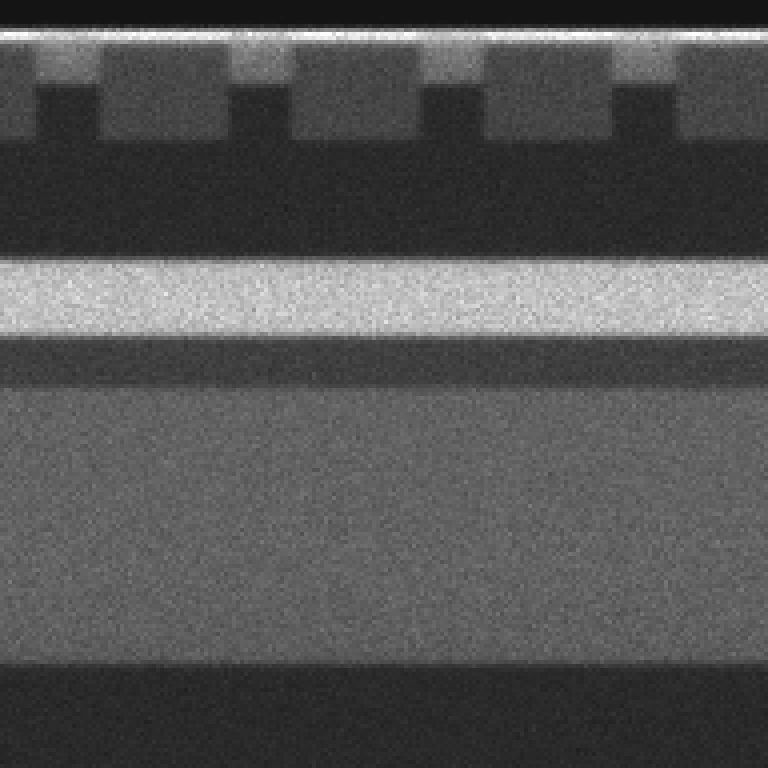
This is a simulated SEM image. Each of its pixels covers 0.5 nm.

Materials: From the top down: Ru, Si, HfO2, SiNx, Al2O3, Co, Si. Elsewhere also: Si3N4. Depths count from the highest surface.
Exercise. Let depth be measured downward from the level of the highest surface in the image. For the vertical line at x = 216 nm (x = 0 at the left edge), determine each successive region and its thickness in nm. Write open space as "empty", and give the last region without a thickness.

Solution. Ru 26, Si 88, HfO2 38, SiNx 26, Al2O3 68, Co 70, Si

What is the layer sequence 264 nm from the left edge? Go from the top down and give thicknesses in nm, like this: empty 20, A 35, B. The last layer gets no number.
Si3N4 54, Si 60, HfO2 38, SiNx 26, Al2O3 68, Co 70, Si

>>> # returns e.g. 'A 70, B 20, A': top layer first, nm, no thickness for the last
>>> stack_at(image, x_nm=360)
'Si3N4 54, Si 60, HfO2 38, SiNx 26, Al2O3 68, Co 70, Si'